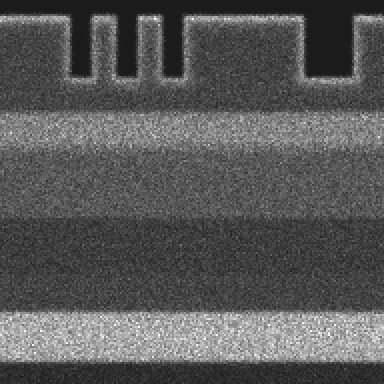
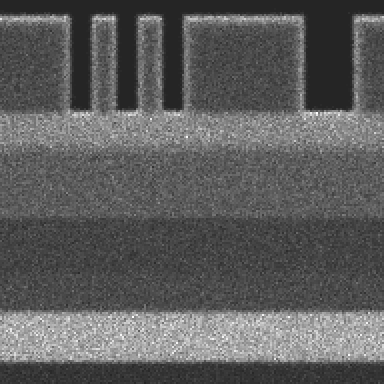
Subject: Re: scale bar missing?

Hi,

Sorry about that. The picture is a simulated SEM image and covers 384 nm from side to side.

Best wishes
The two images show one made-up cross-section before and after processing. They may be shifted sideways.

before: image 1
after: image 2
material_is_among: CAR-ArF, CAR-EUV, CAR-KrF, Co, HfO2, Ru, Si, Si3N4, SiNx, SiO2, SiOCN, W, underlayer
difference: underlayer, removed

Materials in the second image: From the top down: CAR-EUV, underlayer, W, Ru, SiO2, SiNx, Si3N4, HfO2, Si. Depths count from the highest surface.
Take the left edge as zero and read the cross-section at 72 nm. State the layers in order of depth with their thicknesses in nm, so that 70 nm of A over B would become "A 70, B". empty 96, W 32, Ru 8, SiO2 66, SiNx 56, Si3N4 38, HfO2 50, Si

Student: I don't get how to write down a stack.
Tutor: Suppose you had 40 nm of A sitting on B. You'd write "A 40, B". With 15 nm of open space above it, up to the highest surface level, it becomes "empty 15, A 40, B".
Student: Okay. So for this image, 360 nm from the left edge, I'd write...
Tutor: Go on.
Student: CAR-EUV 62, underlayer 34, W 32, Ru 8, SiO2 66, SiNx 56, Si3N4 38, HfO2 50, Si